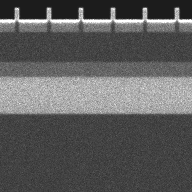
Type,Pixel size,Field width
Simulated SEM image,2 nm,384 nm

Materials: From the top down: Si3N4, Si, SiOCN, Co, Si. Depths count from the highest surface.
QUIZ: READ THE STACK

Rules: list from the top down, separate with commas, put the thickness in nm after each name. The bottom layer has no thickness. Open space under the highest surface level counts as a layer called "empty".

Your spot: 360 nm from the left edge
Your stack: empty 24, Si3N4 24, Si 60, SiOCN 30, Co 74, Si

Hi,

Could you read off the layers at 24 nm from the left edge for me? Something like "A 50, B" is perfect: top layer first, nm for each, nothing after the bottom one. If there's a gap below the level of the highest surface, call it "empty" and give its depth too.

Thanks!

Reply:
empty 24, Si3N4 24, Si 60, SiOCN 30, Co 74, Si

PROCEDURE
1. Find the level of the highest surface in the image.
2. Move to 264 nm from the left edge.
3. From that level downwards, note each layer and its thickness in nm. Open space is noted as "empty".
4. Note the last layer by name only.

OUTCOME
empty 24, Si3N4 24, Si 60, SiOCN 30, Co 74, Si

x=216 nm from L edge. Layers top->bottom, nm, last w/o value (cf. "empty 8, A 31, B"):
empty 24, Si3N4 24, Si 60, SiOCN 30, Co 74, Si